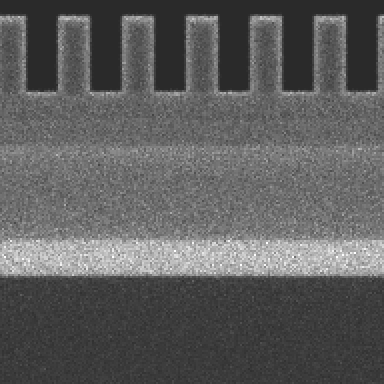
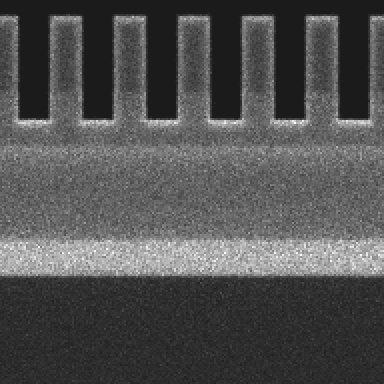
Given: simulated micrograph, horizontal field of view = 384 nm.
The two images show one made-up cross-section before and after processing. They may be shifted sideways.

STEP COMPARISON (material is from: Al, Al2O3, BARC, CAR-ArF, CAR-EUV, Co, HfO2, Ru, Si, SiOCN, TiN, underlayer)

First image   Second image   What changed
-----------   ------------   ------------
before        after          TiN, removed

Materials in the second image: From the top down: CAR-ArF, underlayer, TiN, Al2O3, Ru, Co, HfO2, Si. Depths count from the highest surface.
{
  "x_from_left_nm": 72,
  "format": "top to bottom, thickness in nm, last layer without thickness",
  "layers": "CAR-ArF 52, underlayer 24, TiN 28, Al2O3 26, Ru 70, Co 24, HfO2 36, Si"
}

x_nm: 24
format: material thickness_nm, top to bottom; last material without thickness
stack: empty 104, Al2O3 26, Ru 70, Co 24, HfO2 36, Si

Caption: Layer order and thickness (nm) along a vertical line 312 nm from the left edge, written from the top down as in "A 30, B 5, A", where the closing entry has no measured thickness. CAR-ArF 52, underlayer 24, TiN 28, Al2O3 26, Ru 70, Co 24, HfO2 36, Si